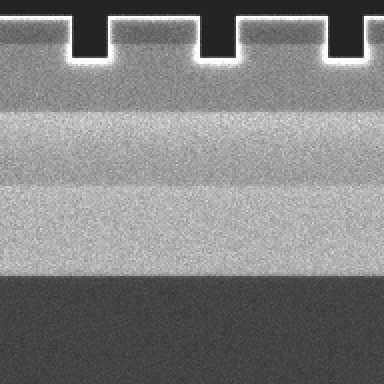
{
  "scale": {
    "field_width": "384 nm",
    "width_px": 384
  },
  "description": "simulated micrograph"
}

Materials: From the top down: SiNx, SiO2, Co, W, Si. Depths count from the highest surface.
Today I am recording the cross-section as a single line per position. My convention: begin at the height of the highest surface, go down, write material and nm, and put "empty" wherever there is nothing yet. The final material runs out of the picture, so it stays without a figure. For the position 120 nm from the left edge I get SiNx 28, SiO2 68, Co 74, W 90, Si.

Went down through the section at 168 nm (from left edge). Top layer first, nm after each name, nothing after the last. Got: SiNx 28, SiO2 68, Co 74, W 90, Si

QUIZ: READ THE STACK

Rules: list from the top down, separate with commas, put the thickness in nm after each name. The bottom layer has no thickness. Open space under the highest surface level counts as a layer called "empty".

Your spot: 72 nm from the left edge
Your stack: empty 42, SiO2 54, Co 74, W 90, Si